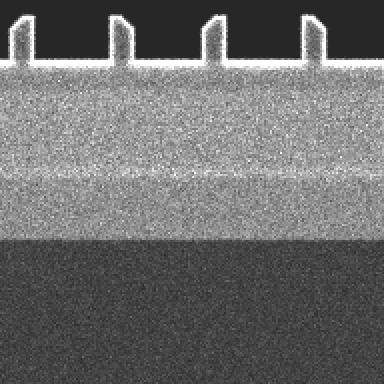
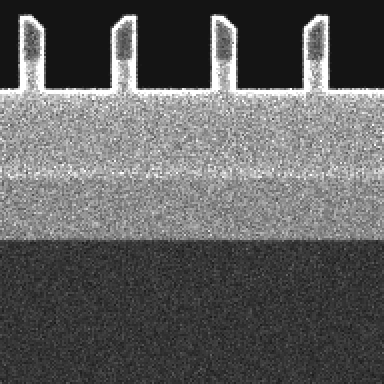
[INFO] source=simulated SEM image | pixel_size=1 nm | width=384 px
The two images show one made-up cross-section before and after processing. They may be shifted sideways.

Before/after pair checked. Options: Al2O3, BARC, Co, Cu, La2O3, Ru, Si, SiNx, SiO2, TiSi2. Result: removed SiO2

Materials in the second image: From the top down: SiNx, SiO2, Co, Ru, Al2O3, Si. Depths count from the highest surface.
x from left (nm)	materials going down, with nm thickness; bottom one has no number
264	empty 74, Co 78, Ru 10, Al2O3 62, Si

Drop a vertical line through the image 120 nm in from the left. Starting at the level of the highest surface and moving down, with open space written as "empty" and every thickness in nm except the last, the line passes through empty 4, SiNx 40, SiO2 30, Co 78, Ru 10, Al2O3 62, Si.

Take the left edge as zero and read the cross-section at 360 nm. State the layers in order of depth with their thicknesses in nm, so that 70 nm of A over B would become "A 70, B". empty 74, Co 78, Ru 10, Al2O3 62, Si